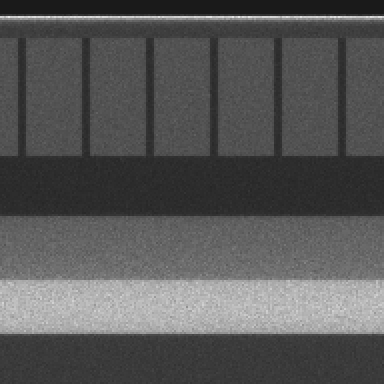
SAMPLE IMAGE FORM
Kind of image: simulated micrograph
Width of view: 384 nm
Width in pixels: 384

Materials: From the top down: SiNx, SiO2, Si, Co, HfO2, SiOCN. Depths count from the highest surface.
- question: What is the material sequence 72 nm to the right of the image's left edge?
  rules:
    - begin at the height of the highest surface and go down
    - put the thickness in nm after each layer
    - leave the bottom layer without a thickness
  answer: SiNx 22, SiO2 118, Si 60, Co 64, HfO2 54, SiOCN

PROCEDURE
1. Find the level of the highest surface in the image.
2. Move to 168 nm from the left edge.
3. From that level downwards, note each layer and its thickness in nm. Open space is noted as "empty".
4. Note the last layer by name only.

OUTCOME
SiNx 22, SiO2 118, Si 60, Co 64, HfO2 54, SiOCN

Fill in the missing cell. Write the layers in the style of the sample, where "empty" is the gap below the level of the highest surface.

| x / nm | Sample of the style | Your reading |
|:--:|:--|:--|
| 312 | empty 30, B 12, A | SiNx 22, SiO2 118, Si 60, Co 64, HfO2 54, SiOCN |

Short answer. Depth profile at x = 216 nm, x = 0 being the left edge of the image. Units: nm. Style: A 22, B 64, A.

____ SiNx 22, Si 178, Co 64, HfO2 54, SiOCN